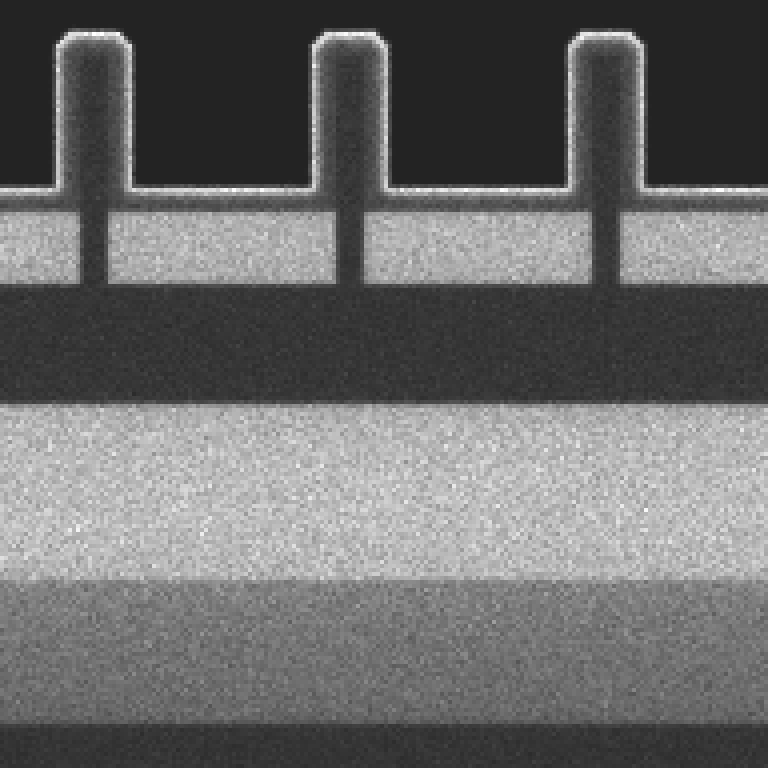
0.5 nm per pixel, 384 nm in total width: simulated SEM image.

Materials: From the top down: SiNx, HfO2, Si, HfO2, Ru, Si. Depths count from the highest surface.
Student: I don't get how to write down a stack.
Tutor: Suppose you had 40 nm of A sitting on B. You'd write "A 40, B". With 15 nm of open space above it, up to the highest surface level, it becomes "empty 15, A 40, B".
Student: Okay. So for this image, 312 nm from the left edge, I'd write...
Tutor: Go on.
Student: SiNx 90, HfO2 36, Si 60, HfO2 88, Ru 72, Si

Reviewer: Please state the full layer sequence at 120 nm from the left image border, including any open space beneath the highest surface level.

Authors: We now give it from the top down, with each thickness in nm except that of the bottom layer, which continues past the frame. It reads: empty 78, SiNx 12, HfO2 36, Si 60, HfO2 88, Ru 72, Si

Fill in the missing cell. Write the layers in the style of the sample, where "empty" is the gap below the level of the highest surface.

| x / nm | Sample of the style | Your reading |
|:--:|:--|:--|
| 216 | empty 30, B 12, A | empty 78, SiNx 12, HfO2 36, Si 60, HfO2 88, Ru 72, Si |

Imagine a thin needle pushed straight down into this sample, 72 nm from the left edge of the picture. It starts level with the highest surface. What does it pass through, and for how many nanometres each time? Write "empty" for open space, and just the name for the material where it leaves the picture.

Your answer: empty 78, SiNx 12, HfO2 36, Si 60, HfO2 88, Ru 72, Si